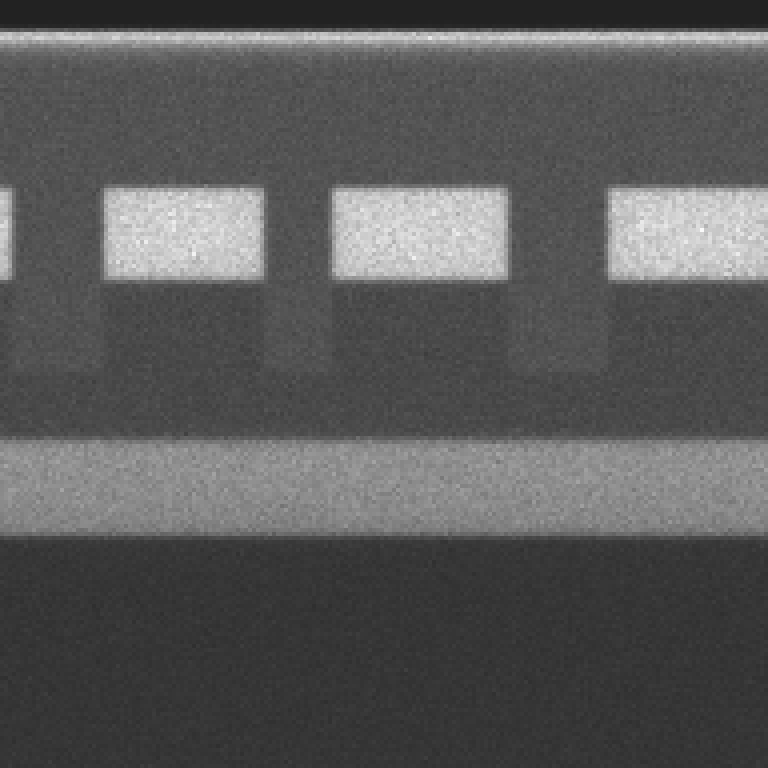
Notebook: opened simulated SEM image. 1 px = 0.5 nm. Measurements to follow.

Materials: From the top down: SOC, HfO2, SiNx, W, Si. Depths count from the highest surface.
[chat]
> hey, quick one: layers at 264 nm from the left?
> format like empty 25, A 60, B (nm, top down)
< SOC 170, SiNx 34, W 48, Si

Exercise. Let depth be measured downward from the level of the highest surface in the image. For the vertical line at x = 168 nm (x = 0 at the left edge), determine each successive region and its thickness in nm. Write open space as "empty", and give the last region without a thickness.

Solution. SOC 78, HfO2 46, SiNx 80, W 48, Si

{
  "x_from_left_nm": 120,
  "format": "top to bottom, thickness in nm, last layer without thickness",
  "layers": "SOC 78, HfO2 46, SiNx 80, W 48, Si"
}